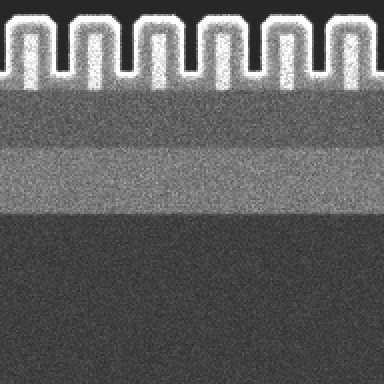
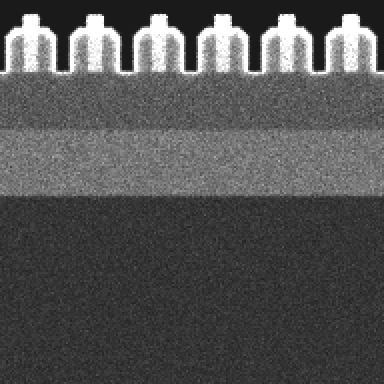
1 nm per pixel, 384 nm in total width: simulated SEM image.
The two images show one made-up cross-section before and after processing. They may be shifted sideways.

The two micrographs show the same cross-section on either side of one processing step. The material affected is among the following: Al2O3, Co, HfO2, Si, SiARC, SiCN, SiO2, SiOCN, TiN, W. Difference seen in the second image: Al2O3 removed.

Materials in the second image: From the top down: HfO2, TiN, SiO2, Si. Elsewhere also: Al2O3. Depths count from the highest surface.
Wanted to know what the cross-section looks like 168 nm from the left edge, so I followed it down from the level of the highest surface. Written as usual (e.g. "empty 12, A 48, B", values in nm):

empty 12, Al2O3 44, TiN 58, SiO2 66, Si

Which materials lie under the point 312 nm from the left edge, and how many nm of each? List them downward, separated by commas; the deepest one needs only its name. empty 56, TiN 58, SiO2 66, Si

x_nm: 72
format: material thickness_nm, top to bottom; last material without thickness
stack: empty 18, Al2O3 38, TiN 58, SiO2 66, Si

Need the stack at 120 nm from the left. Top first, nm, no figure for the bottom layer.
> empty 56, TiN 58, SiO2 66, Si